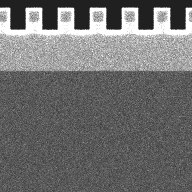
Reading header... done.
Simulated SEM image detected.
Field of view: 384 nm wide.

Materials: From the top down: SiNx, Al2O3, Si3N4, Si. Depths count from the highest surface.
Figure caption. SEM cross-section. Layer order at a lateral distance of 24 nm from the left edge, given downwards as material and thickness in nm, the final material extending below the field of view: empty 44, Al2O3 8, Si3N4 74, Si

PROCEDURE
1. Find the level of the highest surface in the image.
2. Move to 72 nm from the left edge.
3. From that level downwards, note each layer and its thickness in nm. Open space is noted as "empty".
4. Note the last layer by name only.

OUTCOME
SiNx 28, Al2O3 24, Si3N4 74, Si